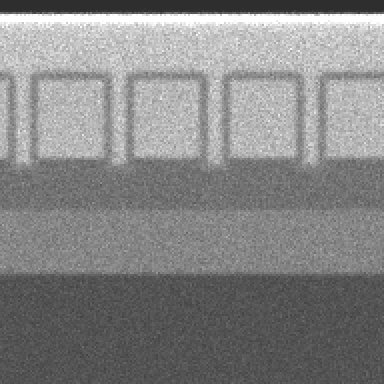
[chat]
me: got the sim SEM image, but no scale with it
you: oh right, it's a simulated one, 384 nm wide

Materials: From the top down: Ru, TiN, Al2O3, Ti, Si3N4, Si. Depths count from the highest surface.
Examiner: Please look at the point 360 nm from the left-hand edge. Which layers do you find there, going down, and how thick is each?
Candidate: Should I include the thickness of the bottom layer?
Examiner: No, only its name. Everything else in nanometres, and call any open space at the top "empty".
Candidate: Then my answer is Ru 56, TiN 8, Al2O3 78, Ti 52, Si3N4 64, Si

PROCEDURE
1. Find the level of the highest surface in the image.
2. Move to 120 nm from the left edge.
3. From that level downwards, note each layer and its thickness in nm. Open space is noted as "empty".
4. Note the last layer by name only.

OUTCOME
Ru 148, TiN 8, Ti 38, Si3N4 64, Si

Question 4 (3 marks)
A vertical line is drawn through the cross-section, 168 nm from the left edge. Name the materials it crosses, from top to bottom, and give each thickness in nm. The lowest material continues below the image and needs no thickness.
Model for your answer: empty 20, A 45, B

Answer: Ru 56, TiN 8, Al2O3 78, Ti 52, Si3N4 64, Si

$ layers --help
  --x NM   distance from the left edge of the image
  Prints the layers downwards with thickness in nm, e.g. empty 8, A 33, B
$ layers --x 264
Ru 56, TiN 8, Al2O3 78, Ti 52, Si3N4 64, Si